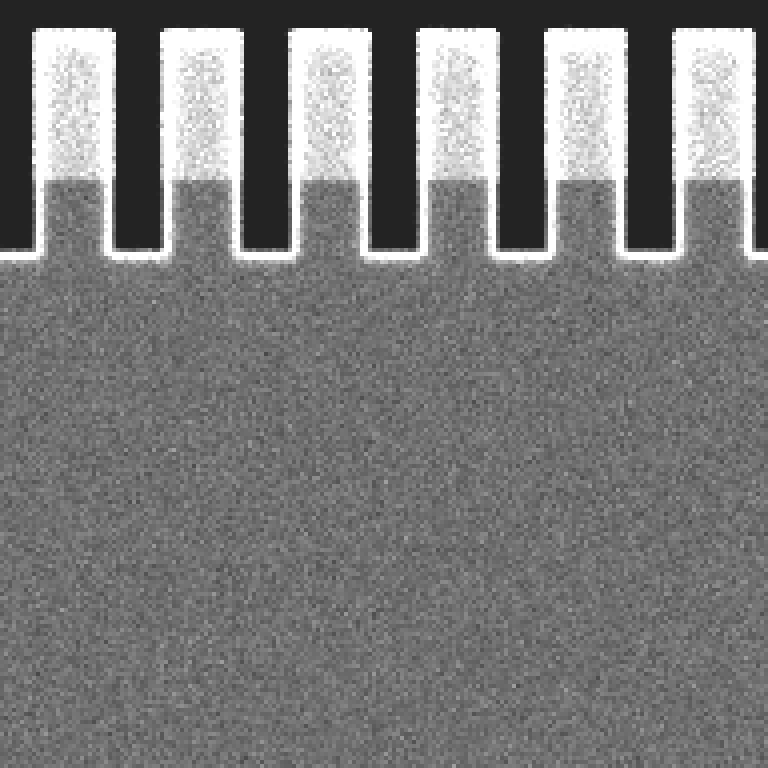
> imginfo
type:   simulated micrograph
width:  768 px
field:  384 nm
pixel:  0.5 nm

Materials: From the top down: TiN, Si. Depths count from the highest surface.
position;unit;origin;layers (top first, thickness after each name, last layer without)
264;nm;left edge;empty 110, Si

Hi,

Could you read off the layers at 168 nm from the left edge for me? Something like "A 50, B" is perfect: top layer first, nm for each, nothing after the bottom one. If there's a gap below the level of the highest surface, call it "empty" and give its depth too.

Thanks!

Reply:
TiN 74, Si